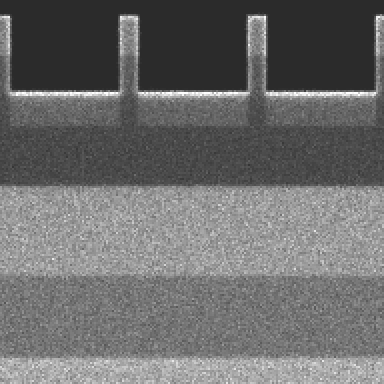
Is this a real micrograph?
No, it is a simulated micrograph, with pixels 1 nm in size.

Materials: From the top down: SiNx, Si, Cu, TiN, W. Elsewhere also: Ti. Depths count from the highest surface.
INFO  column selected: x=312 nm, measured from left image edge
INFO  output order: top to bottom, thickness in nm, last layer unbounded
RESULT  empty 76, SiNx 34, Si 60, Cu 90, TiN 82, W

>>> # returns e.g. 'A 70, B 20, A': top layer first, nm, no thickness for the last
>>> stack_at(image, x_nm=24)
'empty 76, SiNx 34, Si 60, Cu 90, TiN 82, W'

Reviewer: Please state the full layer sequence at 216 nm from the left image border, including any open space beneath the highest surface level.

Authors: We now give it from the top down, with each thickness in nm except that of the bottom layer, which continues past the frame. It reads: empty 76, SiNx 34, Si 60, Cu 90, TiN 82, W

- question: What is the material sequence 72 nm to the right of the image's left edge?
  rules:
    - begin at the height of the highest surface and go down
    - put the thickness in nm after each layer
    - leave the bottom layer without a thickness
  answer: empty 76, SiNx 34, Si 60, Cu 90, TiN 82, W